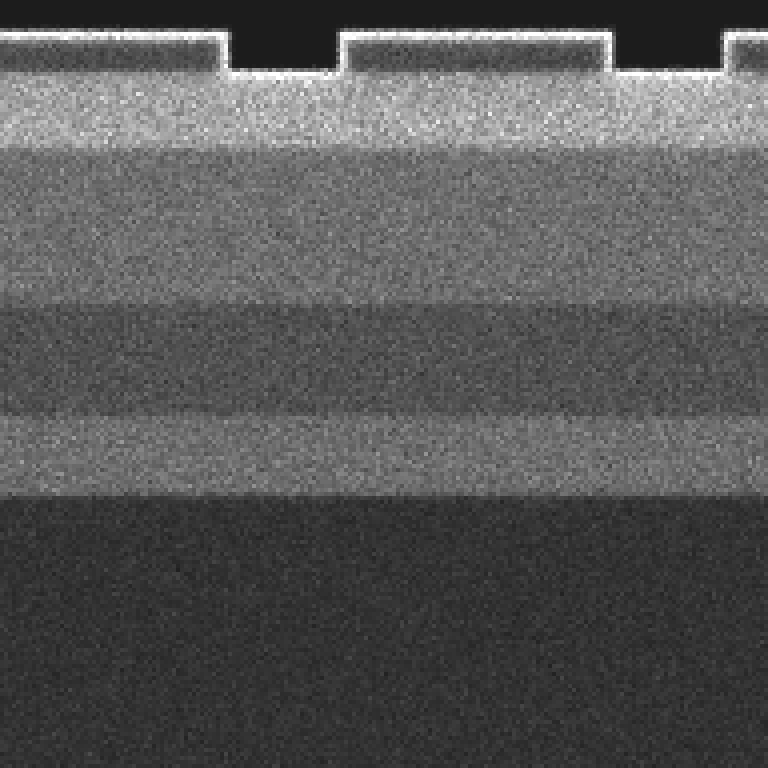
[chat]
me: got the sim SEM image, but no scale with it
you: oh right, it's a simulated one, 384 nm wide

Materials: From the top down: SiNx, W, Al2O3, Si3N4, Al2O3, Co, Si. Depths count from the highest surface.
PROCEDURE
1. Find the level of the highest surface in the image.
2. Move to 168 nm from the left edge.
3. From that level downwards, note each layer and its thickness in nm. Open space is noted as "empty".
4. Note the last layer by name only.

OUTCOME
empty 20, W 38, Al2O3 78, Si3N4 56, Al2O3 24, Co 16, Si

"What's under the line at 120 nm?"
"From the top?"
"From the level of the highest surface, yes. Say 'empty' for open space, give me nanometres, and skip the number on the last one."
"empty 20, W 38, Al2O3 78, Si3N4 56, Al2O3 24, Co 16, Si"